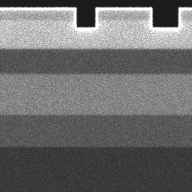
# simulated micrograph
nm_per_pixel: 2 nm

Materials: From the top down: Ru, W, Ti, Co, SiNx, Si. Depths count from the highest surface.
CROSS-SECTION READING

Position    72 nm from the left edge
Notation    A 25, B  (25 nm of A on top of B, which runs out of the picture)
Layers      Ru 24, W 58, Ti 50, Co 82, SiNx 64, Si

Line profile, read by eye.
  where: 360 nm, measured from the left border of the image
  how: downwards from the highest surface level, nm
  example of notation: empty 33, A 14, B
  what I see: Ru 24, W 58, Ti 50, Co 82, SiNx 64, Si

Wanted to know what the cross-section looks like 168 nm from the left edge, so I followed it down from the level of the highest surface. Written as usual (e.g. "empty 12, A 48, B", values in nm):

empty 40, W 42, Ti 50, Co 82, SiNx 64, Si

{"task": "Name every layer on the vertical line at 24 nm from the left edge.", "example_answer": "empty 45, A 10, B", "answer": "Ru 24, W 58, Ti 50, Co 82, SiNx 64, Si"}